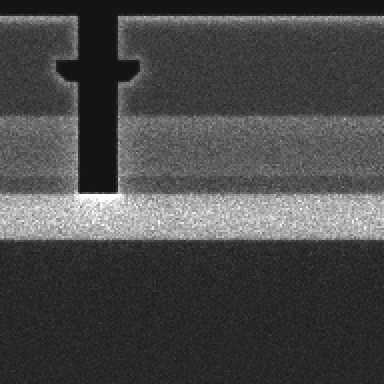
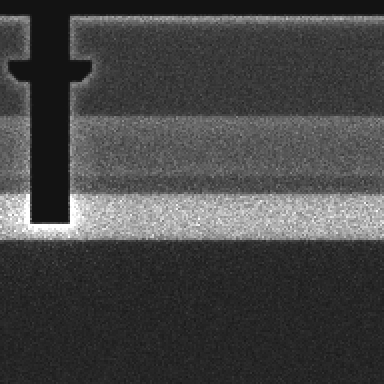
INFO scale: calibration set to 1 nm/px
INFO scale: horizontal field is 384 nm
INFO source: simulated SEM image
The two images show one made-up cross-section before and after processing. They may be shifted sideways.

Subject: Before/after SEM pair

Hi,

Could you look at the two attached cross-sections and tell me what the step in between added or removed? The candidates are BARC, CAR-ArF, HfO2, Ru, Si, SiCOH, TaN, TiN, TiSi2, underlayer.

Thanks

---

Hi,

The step removed HfO2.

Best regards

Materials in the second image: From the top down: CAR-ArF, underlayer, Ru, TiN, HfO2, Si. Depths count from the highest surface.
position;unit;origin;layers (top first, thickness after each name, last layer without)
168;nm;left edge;CAR-ArF 44, underlayer 56, Ru 60, TiN 18, HfO2 46, Si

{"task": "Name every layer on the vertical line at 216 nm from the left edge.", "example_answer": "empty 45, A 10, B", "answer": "CAR-ArF 44, underlayer 56, Ru 60, TiN 18, HfO2 46, Si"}